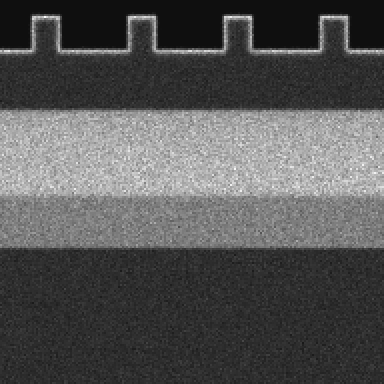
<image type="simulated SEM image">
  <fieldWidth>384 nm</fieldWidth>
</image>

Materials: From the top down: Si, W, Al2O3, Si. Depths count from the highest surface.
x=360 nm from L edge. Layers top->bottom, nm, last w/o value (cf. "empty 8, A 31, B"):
empty 34, Si 60, W 86, Al2O3 52, Si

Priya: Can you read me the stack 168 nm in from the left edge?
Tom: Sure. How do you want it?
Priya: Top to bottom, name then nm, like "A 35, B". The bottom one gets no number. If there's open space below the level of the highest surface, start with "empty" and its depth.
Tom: empty 34, Si 60, W 86, Al2O3 52, Si